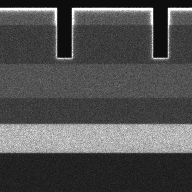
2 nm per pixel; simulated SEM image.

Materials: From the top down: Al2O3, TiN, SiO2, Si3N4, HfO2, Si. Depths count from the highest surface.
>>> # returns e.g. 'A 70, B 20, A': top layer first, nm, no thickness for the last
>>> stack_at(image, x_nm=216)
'Al2O3 34, TiN 78, SiO2 68, Si3N4 52, HfO2 58, Si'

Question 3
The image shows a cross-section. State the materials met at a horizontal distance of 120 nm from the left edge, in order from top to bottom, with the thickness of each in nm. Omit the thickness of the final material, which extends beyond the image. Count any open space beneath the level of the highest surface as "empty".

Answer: empty 100, TiN 12, SiO2 68, Si3N4 52, HfO2 58, Si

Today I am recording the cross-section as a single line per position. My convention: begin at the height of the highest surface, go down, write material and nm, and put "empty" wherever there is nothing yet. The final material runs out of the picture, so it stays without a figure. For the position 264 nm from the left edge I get Al2O3 34, TiN 78, SiO2 68, Si3N4 52, HfO2 58, Si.